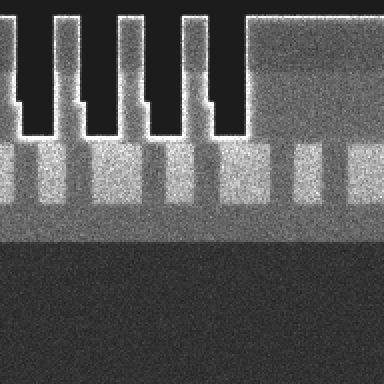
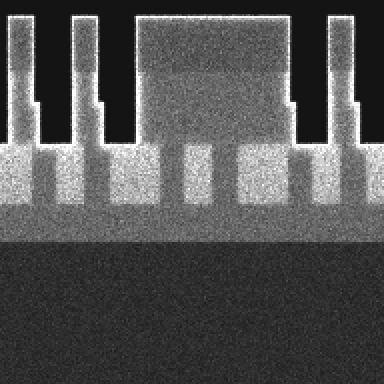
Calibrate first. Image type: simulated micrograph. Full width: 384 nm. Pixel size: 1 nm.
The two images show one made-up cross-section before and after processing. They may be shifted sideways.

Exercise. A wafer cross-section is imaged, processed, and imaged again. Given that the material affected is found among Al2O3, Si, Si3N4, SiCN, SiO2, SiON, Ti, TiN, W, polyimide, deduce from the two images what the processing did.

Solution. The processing removed Al2O3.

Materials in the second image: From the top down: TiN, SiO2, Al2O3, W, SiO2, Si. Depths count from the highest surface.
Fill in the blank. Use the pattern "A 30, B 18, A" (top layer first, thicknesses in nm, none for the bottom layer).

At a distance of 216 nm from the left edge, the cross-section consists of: TiN 56, SiO2 64, Al2O3 8, SiO2 98, Si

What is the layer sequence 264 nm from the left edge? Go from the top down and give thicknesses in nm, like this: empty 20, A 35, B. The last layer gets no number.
TiN 56, SiO2 64, Al2O3 8, W 60, SiO2 38, Si